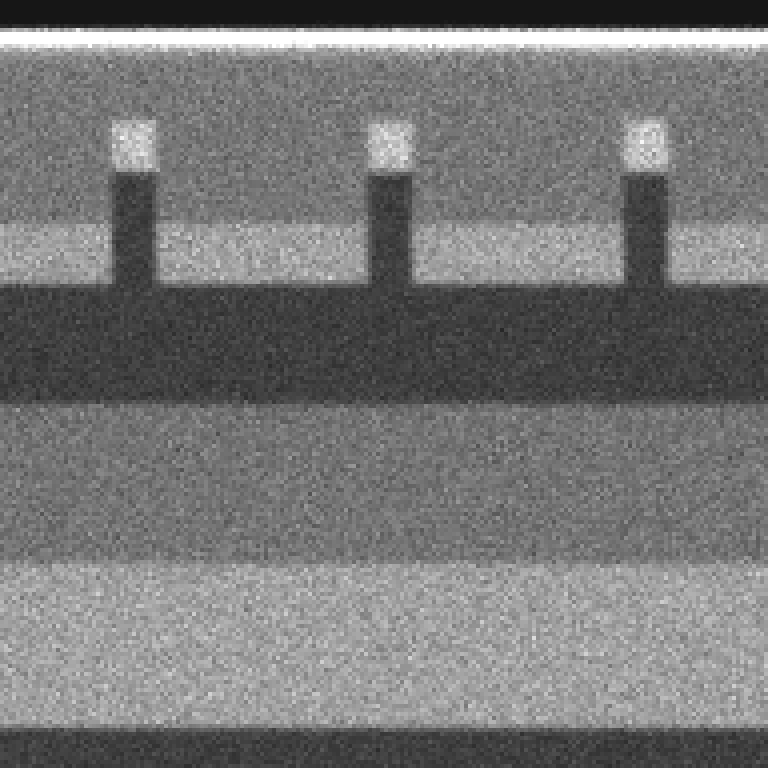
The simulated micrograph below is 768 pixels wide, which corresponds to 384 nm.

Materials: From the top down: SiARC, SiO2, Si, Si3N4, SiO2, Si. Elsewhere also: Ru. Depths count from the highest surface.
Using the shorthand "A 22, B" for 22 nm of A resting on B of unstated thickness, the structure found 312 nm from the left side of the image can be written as SiARC 44, Ru 26, Si 116, Si3N4 80, SiO2 82, Si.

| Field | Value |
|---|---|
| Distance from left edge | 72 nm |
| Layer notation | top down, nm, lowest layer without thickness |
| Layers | SiARC 44, Ru 26, Si 116, Si3N4 80, SiO2 82, Si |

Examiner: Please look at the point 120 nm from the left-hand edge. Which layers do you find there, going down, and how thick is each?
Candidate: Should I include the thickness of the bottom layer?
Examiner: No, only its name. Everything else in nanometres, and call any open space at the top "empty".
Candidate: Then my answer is SiARC 96, SiO2 30, Si 60, Si3N4 80, SiO2 82, Si